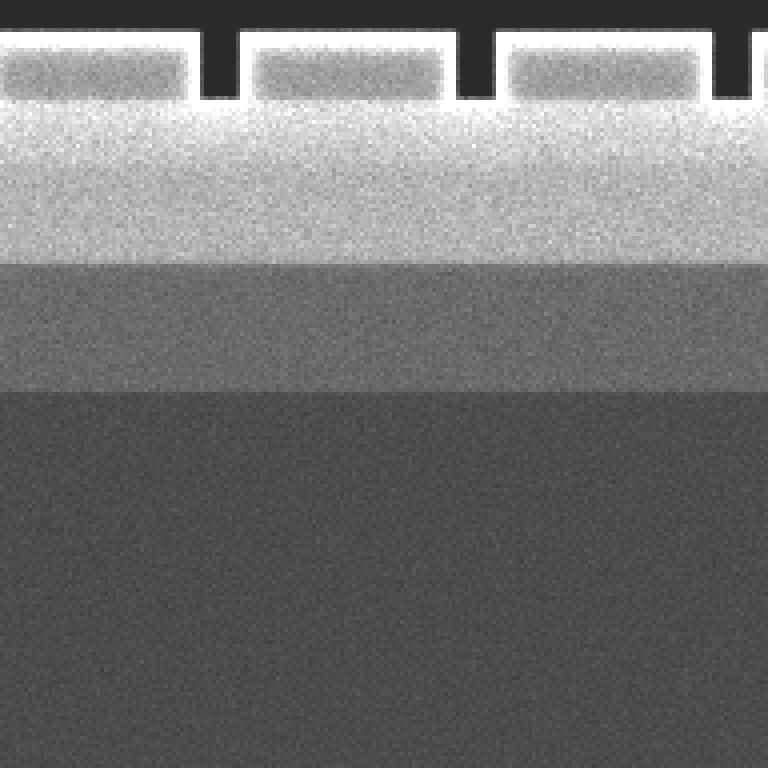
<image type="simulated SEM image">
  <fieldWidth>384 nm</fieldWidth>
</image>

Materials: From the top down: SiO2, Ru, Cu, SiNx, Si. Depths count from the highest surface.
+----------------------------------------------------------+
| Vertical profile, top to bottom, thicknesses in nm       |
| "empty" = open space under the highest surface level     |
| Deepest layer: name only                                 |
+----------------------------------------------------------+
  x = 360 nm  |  empty 34, Ru 32, Cu 50, SiNx 64, Si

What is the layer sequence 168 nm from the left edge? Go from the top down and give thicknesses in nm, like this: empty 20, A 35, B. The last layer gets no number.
SiO2 34, Ru 32, Cu 50, SiNx 64, Si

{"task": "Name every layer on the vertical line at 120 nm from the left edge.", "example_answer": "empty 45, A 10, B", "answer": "SiO2 34, Ru 32, Cu 50, SiNx 64, Si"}